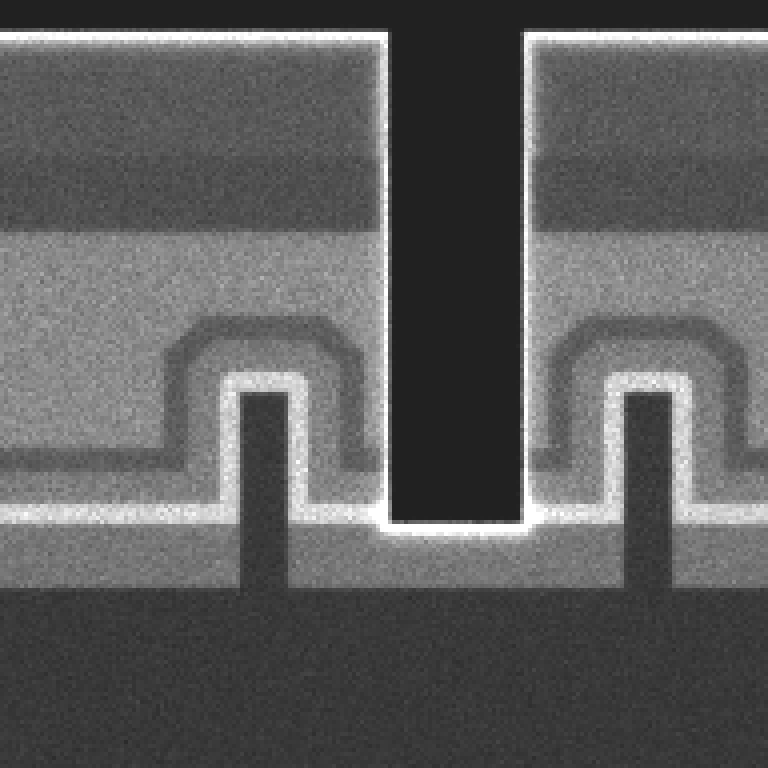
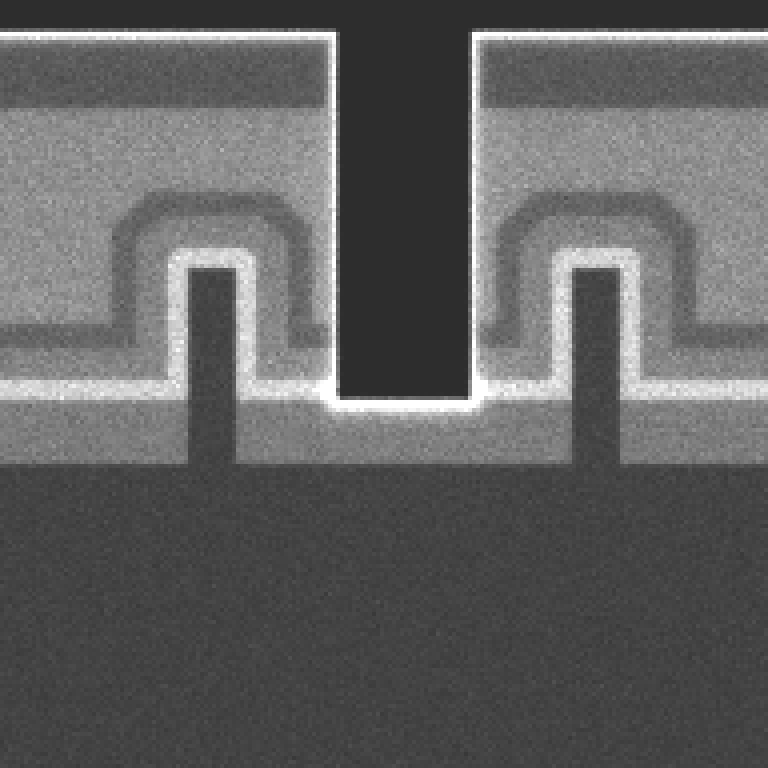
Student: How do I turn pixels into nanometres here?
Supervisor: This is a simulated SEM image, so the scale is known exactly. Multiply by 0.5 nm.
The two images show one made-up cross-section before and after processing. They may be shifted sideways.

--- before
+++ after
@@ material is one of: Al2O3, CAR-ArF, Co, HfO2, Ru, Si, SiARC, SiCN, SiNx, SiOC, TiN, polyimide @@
SiARC removed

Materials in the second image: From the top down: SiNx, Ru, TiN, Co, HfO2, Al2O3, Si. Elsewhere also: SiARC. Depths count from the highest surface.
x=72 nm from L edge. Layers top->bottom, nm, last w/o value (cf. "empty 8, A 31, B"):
SiNx 38, Ru 44, TiN 18, Co 74, HfO2 10, Al2O3 32, Si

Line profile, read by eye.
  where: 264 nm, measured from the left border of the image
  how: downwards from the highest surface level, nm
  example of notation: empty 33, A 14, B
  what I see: SiNx 38, Ru 44, TiN 18, Co 74, HfO2 10, Al2O3 32, Si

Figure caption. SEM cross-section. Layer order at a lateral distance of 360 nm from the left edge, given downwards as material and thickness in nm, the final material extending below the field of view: SiNx 38, Ru 108, TiN 12, Co 16, HfO2 10, Al2O3 32, Si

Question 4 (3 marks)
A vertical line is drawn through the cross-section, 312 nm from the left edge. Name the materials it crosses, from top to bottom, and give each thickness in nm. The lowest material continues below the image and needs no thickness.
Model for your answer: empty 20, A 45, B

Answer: SiNx 38, Ru 42, TiN 12, Co 16, HfO2 76, Al2O3 32, Si